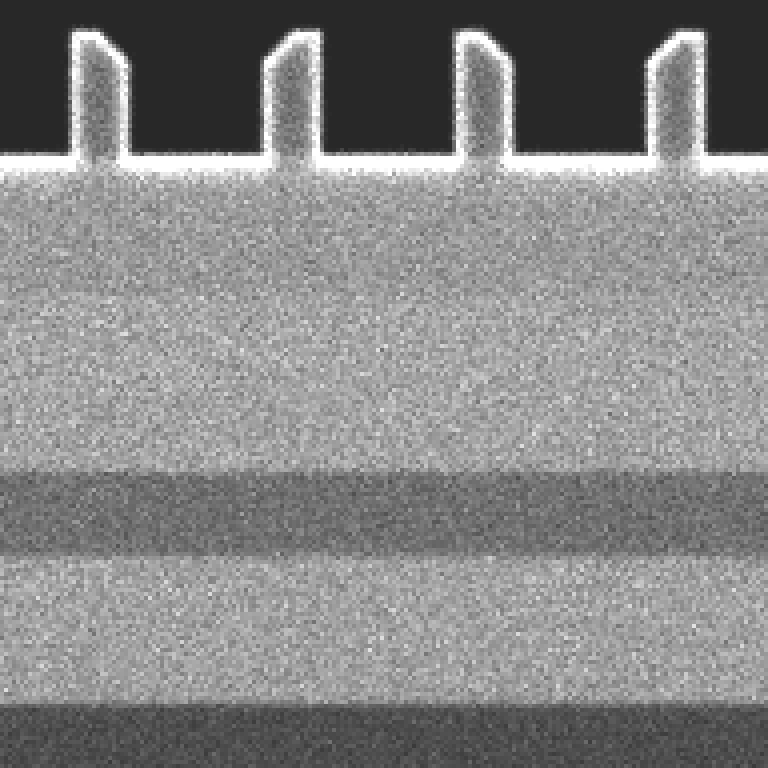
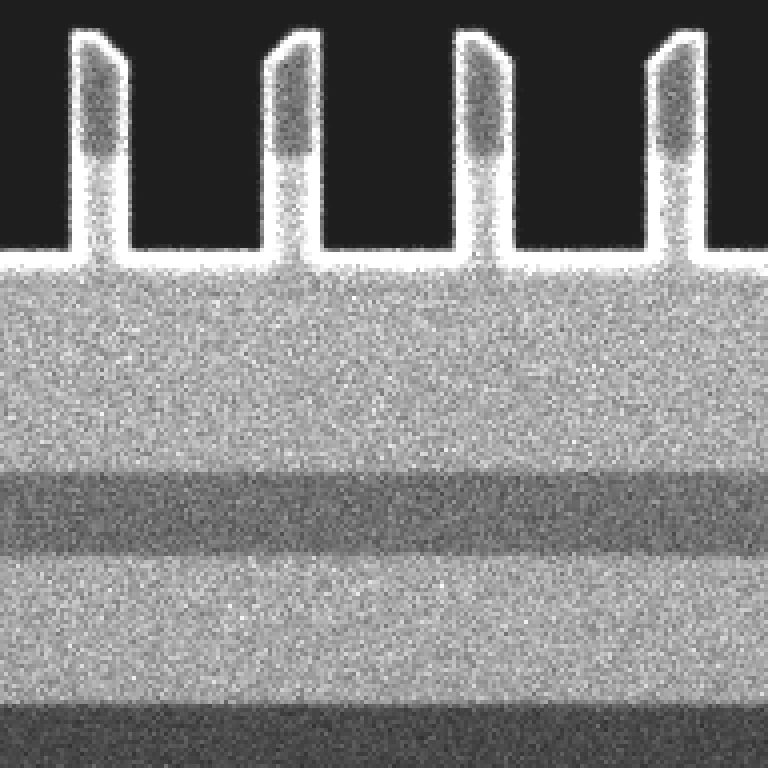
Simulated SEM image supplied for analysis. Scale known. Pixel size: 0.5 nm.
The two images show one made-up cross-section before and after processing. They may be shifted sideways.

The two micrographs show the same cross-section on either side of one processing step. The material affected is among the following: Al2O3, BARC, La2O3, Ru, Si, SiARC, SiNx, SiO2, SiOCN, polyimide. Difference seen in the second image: SiO2 removed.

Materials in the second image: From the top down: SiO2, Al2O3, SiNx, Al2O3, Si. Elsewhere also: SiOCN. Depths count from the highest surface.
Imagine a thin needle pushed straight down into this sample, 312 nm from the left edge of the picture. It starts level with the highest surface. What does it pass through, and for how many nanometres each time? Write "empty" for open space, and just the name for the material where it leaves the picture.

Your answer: empty 110, SiO2 22, Al2O3 88, SiNx 42, Al2O3 74, Si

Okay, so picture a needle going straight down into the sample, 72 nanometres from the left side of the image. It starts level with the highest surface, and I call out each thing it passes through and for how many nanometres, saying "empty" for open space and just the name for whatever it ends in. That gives empty 110, SiO2 22, Al2O3 88, SiNx 42, Al2O3 74, Si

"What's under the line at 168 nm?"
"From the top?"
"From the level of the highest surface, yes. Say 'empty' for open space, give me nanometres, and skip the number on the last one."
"empty 110, SiO2 22, Al2O3 88, SiNx 42, Al2O3 74, Si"